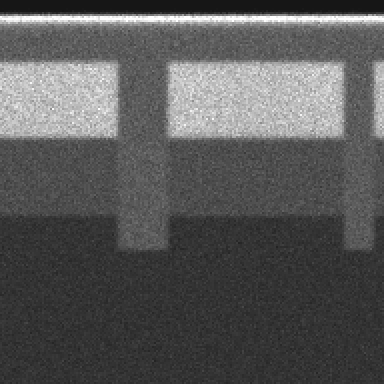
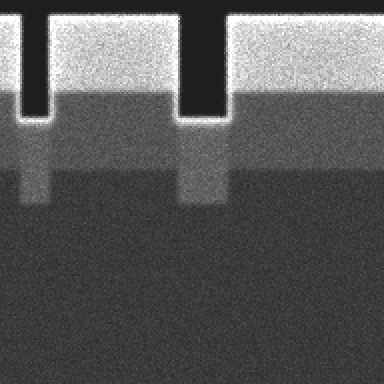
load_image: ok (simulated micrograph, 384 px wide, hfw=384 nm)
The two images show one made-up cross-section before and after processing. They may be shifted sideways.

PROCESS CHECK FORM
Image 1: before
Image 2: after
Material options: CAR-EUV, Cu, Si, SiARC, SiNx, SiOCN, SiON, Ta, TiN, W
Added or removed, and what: removed, SiARC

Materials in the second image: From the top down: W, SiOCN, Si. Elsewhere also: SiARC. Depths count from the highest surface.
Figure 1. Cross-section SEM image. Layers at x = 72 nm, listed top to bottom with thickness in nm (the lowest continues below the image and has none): W 76, SiOCN 78, Si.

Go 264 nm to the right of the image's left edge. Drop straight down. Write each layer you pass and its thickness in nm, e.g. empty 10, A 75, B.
W 76, SiOCN 78, Si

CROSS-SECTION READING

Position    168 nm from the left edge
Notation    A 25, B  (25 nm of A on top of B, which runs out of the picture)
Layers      W 76, SiOCN 78, Si